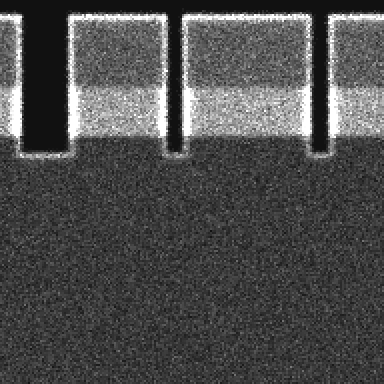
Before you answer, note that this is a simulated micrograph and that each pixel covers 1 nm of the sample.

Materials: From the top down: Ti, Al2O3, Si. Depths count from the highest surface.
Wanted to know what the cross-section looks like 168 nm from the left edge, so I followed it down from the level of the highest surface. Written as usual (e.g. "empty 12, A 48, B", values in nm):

empty 138, Si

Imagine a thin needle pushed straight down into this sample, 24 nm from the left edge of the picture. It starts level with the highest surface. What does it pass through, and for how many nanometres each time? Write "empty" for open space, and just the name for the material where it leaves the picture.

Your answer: empty 138, Si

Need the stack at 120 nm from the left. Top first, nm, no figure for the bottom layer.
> Ti 72, Al2O3 48, Si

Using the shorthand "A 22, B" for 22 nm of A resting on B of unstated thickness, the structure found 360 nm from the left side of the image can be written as Ti 72, Al2O3 48, Si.